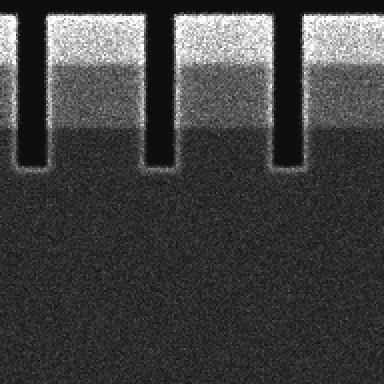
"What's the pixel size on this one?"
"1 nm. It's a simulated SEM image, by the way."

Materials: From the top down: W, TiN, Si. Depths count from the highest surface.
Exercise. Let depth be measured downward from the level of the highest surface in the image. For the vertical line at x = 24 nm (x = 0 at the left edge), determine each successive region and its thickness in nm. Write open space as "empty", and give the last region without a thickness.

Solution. empty 152, Si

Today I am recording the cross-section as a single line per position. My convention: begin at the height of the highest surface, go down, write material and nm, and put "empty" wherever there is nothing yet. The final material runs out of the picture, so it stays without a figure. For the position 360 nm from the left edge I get W 48, TiN 64, Si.